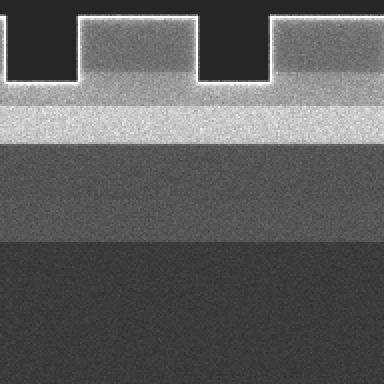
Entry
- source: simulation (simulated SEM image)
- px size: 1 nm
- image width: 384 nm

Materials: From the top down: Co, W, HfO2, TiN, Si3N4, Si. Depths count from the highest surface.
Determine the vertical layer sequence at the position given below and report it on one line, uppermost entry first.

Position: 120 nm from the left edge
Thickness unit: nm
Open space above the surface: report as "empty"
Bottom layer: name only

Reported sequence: Co 56, W 34, HfO2 38, TiN 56, Si3N4 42, Si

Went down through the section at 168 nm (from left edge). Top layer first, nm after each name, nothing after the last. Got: Co 56, W 34, HfO2 38, TiN 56, Si3N4 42, Si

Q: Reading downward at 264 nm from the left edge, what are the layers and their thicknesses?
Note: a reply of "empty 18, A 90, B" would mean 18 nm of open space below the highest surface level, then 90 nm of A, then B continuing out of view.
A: empty 66, W 24, HfO2 38, TiN 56, Si3N4 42, Si